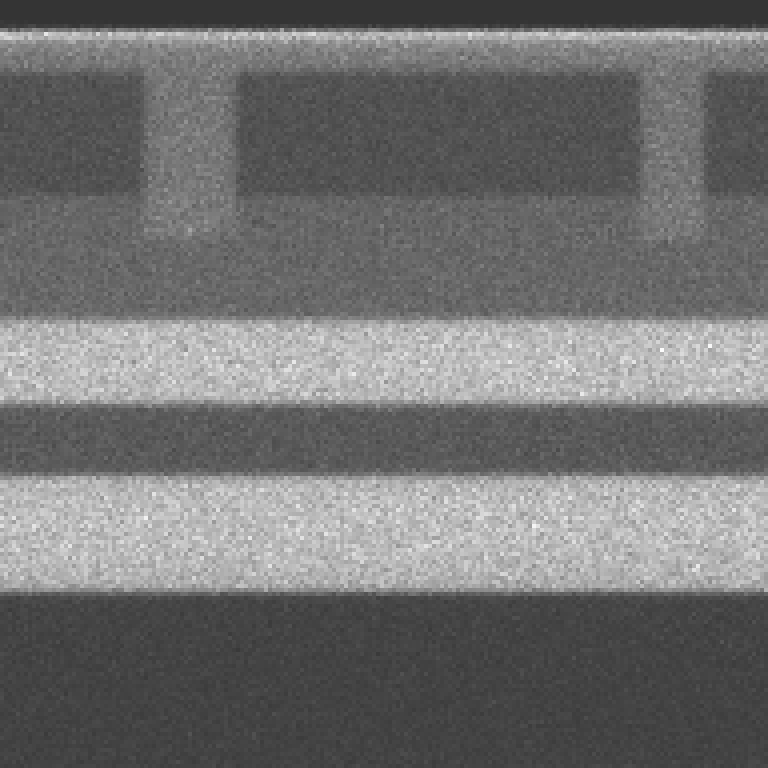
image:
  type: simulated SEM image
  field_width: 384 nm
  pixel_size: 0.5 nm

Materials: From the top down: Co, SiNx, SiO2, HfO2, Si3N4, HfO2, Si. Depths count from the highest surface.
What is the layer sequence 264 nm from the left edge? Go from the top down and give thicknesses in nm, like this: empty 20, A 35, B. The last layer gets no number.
Co 20, SiNx 62, SiO2 62, HfO2 42, Si3N4 36, HfO2 58, Si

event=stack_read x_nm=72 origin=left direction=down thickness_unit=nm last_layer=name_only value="Co 104, SiO2 40, HfO2 42, Si3N4 36, HfO2 58, Si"